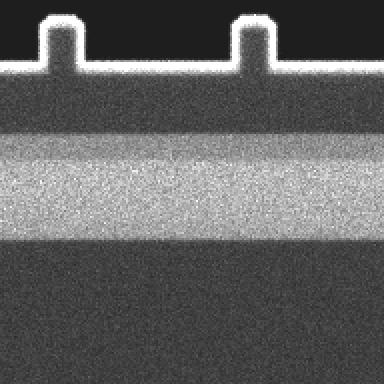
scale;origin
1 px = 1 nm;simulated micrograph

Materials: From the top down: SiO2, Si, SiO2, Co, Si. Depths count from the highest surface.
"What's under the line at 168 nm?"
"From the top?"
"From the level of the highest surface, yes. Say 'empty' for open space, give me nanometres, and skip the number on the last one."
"empty 46, SiO2 12, Si 60, SiO2 26, Co 80, Si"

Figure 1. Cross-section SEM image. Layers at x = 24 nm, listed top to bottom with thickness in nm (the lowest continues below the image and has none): empty 46, SiO2 12, Si 60, SiO2 26, Co 80, Si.